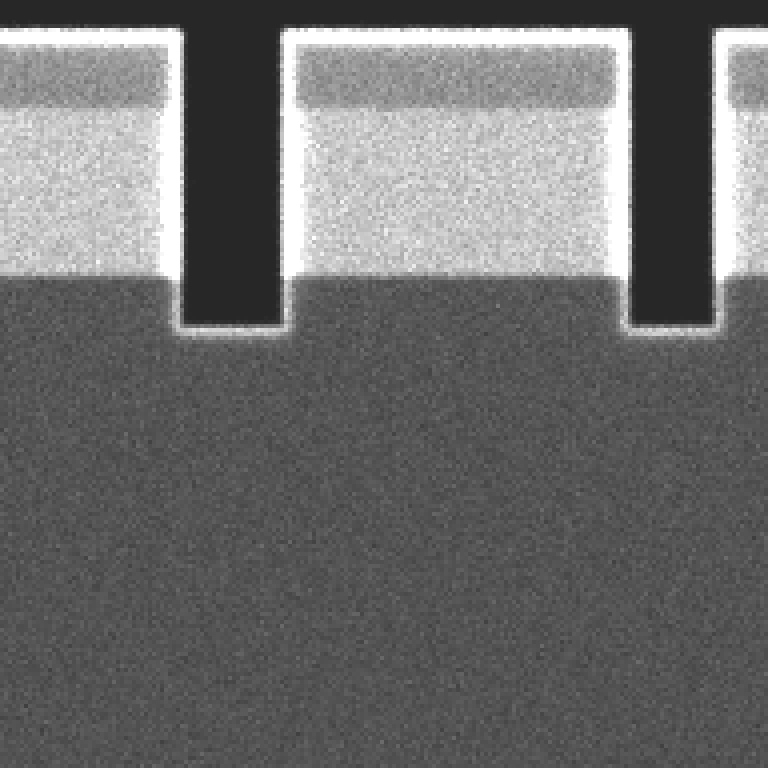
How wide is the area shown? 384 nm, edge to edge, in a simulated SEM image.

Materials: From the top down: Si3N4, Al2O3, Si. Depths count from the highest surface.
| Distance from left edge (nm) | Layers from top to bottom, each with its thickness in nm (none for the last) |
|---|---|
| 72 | Si3N4 38, Al2O3 84, Si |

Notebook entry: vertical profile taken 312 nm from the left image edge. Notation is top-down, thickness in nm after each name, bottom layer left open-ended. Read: Si3N4 38, Al2O3 84, Si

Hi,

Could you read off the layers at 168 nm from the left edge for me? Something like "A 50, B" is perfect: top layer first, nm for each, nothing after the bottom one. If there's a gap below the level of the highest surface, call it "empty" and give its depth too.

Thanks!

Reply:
Si3N4 38, Al2O3 84, Si